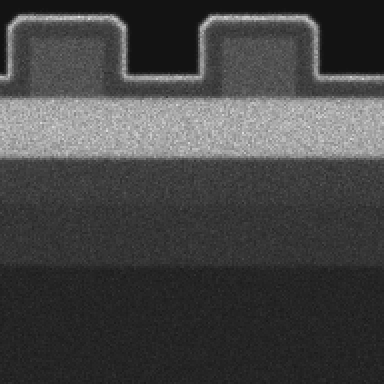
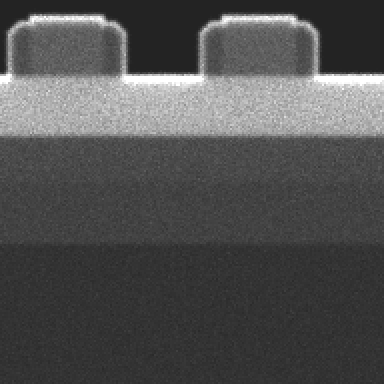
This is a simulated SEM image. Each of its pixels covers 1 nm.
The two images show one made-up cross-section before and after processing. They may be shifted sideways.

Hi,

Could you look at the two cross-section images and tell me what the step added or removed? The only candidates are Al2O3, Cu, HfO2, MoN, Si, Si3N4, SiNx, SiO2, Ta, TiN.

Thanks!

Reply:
removed Si3N4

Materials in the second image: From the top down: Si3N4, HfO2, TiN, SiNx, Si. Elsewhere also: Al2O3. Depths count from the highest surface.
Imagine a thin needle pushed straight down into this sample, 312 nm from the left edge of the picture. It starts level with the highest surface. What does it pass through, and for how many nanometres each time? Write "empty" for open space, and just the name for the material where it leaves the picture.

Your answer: empty 12, Si3N4 48, HfO2 60, TiN 46, SiNx 62, Si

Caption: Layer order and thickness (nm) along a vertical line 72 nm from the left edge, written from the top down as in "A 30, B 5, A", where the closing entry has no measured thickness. Al2O3 60, HfO2 60, TiN 46, SiNx 62, Si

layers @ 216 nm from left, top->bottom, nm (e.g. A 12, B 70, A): empty 6, Si3N4 54, HfO2 60, TiN 46, SiNx 62, Si